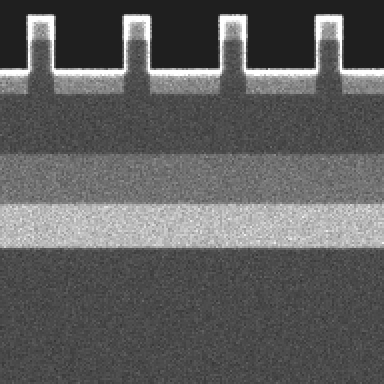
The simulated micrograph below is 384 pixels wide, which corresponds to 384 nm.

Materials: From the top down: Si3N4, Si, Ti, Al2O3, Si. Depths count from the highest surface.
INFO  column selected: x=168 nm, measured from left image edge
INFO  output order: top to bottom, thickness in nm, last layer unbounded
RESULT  empty 54, Si3N4 24, Si 60, Ti 50, Al2O3 44, Si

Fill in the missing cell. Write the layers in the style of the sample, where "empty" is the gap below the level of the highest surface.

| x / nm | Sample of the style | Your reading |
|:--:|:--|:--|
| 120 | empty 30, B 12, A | empty 54, Si3N4 24, Si 60, Ti 50, Al2O3 44, Si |